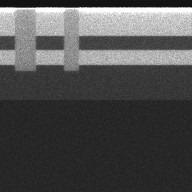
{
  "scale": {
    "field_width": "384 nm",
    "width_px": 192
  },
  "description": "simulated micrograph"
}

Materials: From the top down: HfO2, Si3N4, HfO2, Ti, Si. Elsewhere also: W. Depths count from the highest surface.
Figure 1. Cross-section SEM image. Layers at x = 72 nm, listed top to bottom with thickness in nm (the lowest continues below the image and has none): HfO2 56, Si3N4 28, HfO2 30, Ti 70, Si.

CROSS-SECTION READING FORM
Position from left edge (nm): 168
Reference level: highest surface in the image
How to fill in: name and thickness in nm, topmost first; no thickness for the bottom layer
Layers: HfO2 56, Si3N4 28, HfO2 30, Ti 70, Si